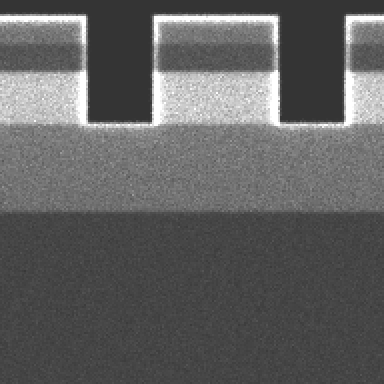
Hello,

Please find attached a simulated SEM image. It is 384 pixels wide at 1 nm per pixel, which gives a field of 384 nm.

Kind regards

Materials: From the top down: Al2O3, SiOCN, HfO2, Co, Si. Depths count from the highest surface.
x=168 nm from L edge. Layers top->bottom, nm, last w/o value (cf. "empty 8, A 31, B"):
Al2O3 28, SiOCN 28, HfO2 52, Co 88, Si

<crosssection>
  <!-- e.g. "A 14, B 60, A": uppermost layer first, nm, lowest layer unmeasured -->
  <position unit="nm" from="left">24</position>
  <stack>Al2O3 28, SiOCN 28, HfO2 52, Co 88, Si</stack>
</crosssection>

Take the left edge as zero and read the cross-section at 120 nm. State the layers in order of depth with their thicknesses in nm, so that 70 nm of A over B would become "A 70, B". empty 108, Co 88, Si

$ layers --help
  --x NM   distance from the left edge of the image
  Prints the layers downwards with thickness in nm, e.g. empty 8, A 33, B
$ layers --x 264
Al2O3 28, SiOCN 28, HfO2 52, Co 88, Si